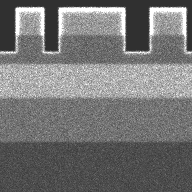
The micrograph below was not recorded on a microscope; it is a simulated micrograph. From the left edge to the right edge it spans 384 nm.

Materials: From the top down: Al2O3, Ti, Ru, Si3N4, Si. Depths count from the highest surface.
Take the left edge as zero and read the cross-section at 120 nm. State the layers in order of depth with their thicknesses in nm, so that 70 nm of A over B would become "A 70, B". Al2O3 54, Ti 58, Ru 68, Si3N4 88, Si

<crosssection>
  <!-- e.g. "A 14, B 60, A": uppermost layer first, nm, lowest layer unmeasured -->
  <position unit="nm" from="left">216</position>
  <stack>Al2O3 54, Ti 58, Ru 68, Si3N4 88, Si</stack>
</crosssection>